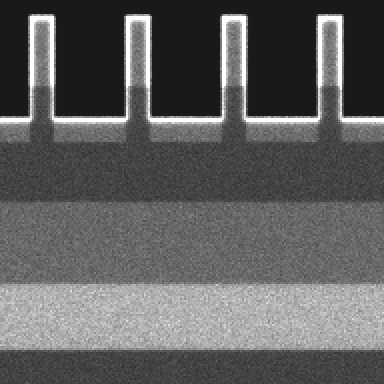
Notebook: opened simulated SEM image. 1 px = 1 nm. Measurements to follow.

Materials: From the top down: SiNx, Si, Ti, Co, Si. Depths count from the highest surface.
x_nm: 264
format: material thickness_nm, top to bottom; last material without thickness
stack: empty 102, SiNx 24, Si 60, Ti 82, Co 66, Si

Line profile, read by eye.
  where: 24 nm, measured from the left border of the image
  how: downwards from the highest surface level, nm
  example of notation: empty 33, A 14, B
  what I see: empty 102, SiNx 24, Si 60, Ti 82, Co 66, Si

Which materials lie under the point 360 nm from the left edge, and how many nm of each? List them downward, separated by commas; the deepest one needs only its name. empty 102, SiNx 24, Si 60, Ti 82, Co 66, Si